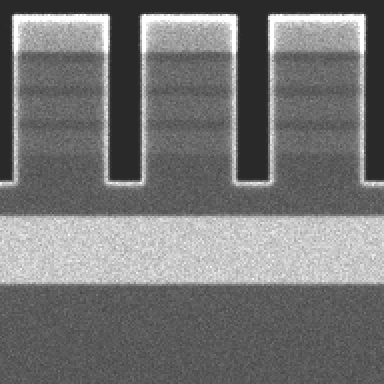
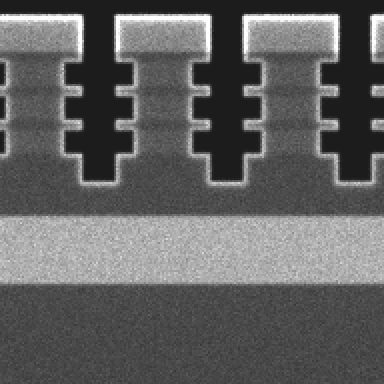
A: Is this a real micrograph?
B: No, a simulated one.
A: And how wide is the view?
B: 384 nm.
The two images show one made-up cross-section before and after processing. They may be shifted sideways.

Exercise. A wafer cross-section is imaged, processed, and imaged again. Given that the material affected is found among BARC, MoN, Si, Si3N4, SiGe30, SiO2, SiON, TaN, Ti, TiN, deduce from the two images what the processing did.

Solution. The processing removed SiGe30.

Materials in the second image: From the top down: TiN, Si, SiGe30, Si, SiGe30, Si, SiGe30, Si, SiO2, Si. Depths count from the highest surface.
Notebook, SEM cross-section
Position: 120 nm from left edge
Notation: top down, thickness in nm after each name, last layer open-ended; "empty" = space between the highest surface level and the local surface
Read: TiN 36, Si 10, empty 24, Si 10, empty 24, Si 10, empty 24, Si 62, SiO2 68, Si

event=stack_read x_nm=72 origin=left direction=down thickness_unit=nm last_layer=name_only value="TiN 36, Si 10, empty 24, Si 10, empty 24, Si 10, empty 24, Si 62, SiO2 68, Si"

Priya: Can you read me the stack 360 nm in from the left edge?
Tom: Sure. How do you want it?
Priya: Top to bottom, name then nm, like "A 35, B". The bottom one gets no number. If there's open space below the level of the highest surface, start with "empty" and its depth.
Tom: empty 166, Si 34, SiO2 68, Si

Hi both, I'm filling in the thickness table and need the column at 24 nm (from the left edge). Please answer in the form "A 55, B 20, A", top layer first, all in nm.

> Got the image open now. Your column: TiN 36, Si 10, SiGe30 24, Si 10, SiGe30 24, Si 10, SiGe30 24, Si 62, SiO2 68, Si